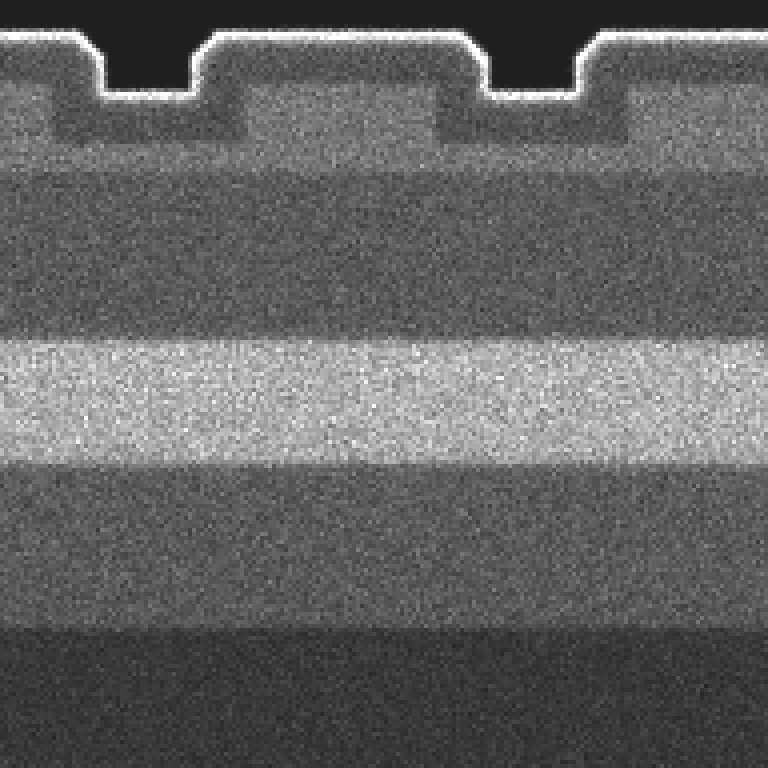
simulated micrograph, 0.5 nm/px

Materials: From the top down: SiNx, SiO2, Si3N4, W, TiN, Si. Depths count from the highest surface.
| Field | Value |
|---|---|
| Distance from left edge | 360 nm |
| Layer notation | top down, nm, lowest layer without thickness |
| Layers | SiNx 26, SiO2 44, Si3N4 84, W 62, TiN 82, Si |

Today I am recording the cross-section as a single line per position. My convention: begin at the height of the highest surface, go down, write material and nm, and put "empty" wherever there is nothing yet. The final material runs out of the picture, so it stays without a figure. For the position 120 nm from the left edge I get SiNx 56, SiO2 14, Si3N4 84, W 62, TiN 82, Si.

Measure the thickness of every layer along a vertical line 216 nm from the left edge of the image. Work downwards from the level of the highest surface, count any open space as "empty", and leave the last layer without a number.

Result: SiNx 26, SiO2 44, Si3N4 84, W 62, TiN 82, Si